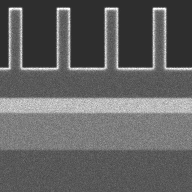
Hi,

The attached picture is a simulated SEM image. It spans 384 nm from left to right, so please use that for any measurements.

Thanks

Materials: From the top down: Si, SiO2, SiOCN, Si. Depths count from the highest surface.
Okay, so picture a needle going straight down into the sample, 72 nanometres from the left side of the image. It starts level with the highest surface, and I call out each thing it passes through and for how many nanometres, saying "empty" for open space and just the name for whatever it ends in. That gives empty 120, Si 60, SiO2 30, SiOCN 74, Si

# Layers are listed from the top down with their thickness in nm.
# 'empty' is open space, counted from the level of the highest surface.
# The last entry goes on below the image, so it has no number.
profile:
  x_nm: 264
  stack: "empty 120, Si 60, SiO2 30, SiOCN 74, Si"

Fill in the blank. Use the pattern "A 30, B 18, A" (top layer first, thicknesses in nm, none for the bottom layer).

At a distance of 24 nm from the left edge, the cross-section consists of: Si 180, SiO2 30, SiOCN 74, Si